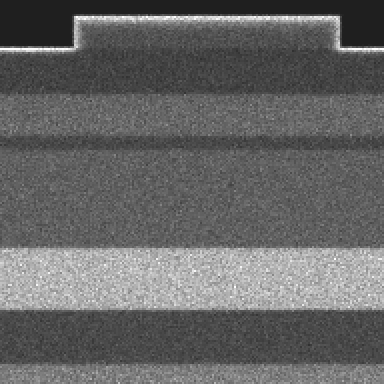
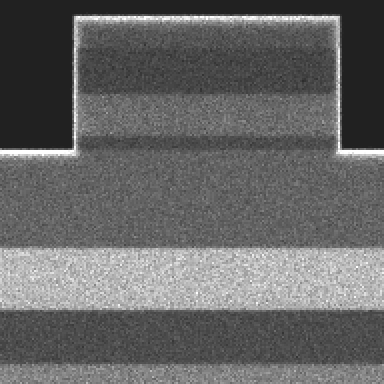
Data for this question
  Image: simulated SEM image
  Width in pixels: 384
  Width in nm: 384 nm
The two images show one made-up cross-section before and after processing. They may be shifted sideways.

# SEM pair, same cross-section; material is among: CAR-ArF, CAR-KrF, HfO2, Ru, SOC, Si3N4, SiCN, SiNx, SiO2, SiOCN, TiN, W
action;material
removed;Ru and SiNx and TiN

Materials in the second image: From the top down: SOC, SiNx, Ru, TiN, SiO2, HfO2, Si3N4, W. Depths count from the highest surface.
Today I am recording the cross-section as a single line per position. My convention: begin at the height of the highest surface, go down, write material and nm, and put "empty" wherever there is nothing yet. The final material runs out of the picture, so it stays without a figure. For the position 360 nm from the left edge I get empty 134, SiO2 98, HfO2 62, Si3N4 54, W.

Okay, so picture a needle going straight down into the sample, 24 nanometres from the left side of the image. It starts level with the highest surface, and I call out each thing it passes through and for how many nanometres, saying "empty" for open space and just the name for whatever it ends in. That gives empty 134, SiO2 98, HfO2 62, Si3N4 54, W